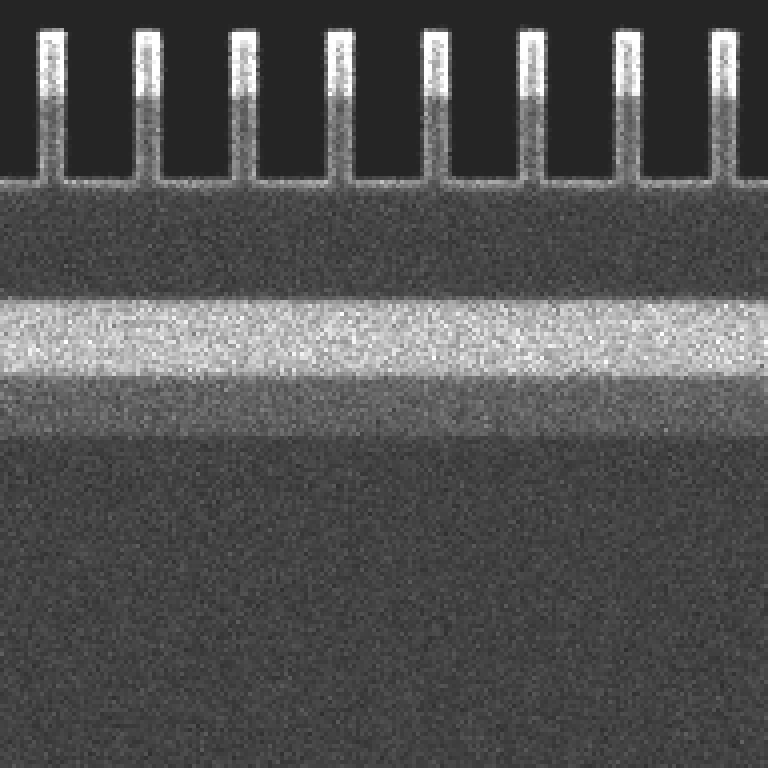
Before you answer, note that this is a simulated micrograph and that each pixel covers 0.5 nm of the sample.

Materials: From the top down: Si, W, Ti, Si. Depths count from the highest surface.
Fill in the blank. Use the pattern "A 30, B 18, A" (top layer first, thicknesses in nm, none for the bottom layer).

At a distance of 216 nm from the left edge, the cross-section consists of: Si 134, W 38, Ti 30, Si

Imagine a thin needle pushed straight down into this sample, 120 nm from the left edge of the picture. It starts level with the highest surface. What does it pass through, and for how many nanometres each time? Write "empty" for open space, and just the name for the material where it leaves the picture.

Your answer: Si 134, W 38, Ti 30, Si